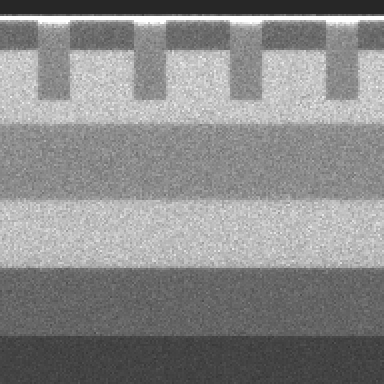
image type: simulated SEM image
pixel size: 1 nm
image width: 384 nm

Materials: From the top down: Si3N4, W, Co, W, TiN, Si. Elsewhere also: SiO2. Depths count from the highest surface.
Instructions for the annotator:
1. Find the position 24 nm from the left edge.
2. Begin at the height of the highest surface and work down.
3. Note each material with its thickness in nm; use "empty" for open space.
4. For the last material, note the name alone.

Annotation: Si3N4 34, W 74, Co 76, W 68, TiN 68, Si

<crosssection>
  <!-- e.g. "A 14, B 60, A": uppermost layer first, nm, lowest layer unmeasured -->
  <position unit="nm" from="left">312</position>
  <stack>Si3N4 34, W 74, Co 76, W 68, TiN 68, Si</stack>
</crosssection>